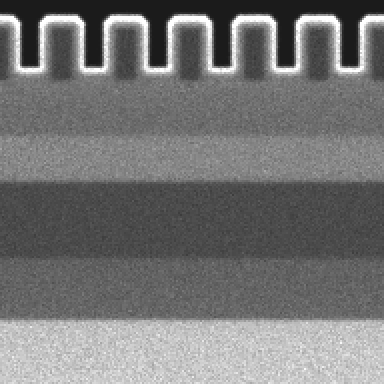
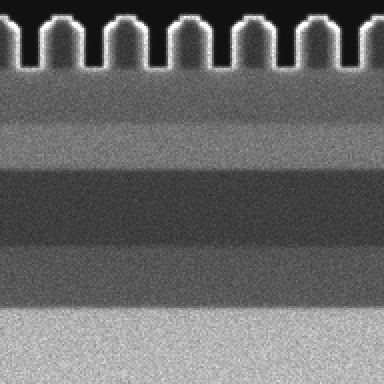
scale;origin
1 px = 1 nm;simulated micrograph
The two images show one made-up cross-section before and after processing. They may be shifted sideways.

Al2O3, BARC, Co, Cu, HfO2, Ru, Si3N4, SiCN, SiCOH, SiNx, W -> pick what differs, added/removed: Al2O3 removed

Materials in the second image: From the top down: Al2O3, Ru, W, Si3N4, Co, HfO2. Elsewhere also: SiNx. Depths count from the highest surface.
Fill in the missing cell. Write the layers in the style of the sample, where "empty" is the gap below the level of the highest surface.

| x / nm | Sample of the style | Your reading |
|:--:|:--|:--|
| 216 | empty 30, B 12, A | empty 52, Ru 56, W 46, Si3N4 76, Co 62, HfO2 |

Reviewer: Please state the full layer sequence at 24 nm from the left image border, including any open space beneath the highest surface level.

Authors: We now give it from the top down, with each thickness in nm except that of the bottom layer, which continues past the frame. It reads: empty 52, Ru 56, W 46, Si3N4 76, Co 62, HfO2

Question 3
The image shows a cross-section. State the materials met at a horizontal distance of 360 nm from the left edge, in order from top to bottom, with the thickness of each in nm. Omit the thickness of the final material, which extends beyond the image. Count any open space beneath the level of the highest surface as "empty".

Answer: empty 12, Al2O3 40, Ru 56, W 46, Si3N4 76, Co 62, HfO2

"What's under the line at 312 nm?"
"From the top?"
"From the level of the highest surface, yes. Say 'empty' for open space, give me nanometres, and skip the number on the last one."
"SiNx 52, Ru 56, W 46, Si3N4 76, Co 62, HfO2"